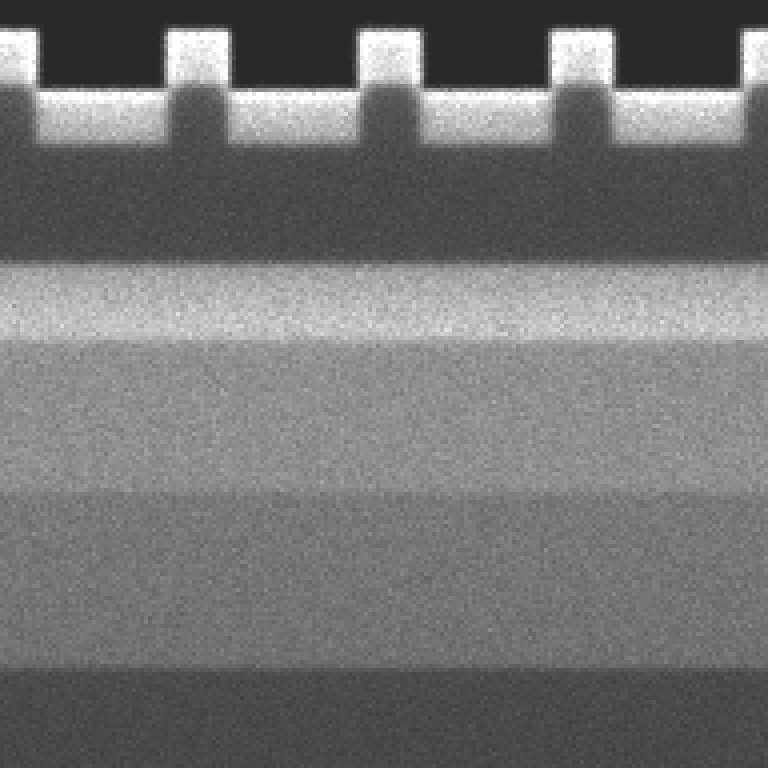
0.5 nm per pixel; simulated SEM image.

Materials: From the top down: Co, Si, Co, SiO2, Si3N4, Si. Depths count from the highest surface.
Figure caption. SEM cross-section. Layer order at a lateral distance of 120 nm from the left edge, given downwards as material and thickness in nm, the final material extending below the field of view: empty 30, Co 26, Si 60, Co 38, SiO2 76, Si3N4 88, Si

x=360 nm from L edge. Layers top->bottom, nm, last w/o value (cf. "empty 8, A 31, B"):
empty 30, Co 26, Si 60, Co 38, SiO2 76, Si3N4 88, Si